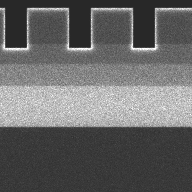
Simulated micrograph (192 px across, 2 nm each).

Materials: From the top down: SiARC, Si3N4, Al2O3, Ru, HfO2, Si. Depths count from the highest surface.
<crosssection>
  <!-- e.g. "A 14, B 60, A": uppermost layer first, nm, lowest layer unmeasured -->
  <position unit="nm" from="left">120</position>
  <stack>SiARC 14, Si3N4 58, Al2O3 40, Ru 44, HfO2 82, Si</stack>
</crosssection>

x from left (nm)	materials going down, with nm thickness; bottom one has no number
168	empty 80, Al2O3 32, Ru 44, HfO2 82, Si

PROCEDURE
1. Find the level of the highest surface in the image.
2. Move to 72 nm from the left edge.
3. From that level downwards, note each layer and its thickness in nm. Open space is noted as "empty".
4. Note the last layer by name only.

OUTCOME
SiARC 14, Si3N4 58, Al2O3 40, Ru 44, HfO2 82, Si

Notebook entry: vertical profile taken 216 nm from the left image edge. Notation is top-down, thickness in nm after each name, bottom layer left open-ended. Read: SiARC 14, Si3N4 58, Al2O3 40, Ru 44, HfO2 82, Si